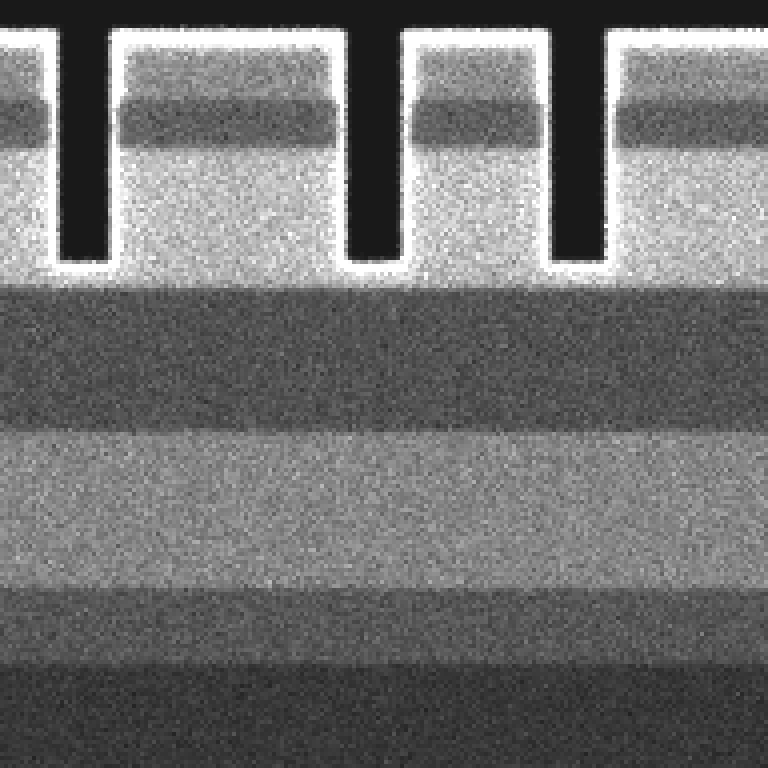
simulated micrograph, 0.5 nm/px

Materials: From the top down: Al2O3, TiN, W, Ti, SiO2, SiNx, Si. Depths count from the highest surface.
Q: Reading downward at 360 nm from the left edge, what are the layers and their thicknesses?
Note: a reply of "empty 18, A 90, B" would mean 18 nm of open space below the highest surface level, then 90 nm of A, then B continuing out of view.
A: Al2O3 34, TiN 24, W 70, Ti 72, SiO2 78, SiNx 38, Si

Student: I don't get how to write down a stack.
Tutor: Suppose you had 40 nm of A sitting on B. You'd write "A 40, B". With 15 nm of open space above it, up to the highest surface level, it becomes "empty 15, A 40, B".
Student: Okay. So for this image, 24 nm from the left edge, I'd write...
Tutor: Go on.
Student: Al2O3 34, TiN 24, W 70, Ti 72, SiO2 78, SiNx 38, Si